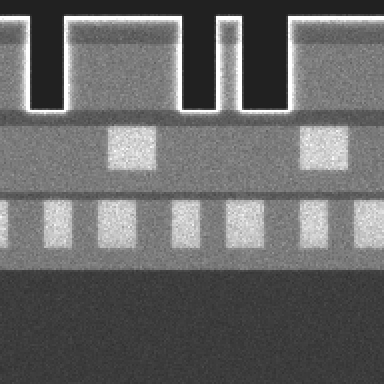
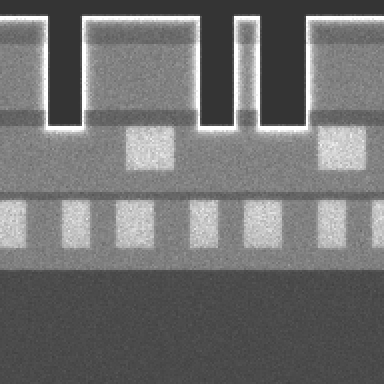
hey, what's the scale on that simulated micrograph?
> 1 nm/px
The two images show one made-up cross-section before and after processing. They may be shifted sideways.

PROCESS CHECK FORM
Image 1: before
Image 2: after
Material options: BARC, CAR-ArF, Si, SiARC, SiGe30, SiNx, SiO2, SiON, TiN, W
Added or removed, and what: removed, SiNx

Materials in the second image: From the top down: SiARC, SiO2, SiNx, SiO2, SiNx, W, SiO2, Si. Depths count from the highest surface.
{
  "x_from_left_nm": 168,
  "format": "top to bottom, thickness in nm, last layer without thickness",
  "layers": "SiARC 28, SiO2 66, SiNx 16, W 44, SiO2 22, SiNx 8, SiO2 70, Si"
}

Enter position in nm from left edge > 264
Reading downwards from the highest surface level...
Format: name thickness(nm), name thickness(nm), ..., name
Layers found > empty 110, SiO2 66, SiNx 8, W 48, SiO2 22, Si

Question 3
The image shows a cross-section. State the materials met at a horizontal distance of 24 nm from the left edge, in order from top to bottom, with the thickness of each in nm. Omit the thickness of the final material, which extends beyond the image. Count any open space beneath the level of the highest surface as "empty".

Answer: SiARC 28, SiO2 66, SiNx 16, SiO2 66, SiNx 8, W 48, SiO2 22, Si